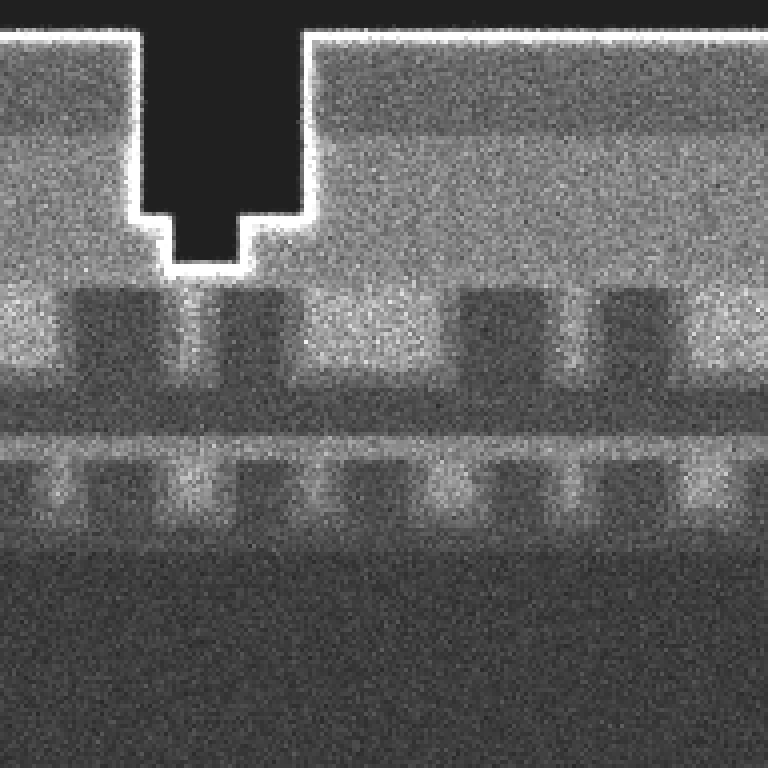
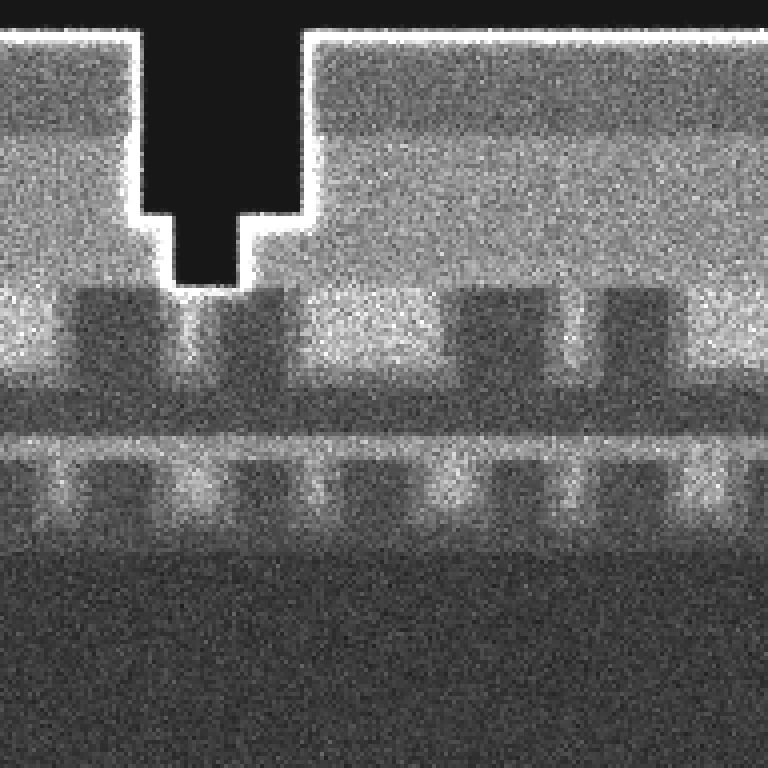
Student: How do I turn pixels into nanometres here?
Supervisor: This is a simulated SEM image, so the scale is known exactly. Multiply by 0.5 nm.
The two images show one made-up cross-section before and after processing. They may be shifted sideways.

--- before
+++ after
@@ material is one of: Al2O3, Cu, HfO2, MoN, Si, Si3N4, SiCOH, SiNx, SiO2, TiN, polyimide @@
Al2O3 removed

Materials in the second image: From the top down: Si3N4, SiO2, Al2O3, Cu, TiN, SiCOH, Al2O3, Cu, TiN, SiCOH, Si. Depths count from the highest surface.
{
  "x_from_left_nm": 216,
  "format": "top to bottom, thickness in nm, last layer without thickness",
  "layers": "Si3N4 52, SiO2 64, Al2O3 12, Cu 40, TiN 10, SiCOH 24, Al2O3 12, Cu 24, TiN 10, SiCOH 12, Si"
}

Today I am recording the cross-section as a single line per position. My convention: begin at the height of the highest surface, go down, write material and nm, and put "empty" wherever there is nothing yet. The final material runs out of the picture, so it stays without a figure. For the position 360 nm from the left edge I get Si3N4 52, SiO2 64, Al2O3 12, Cu 40, TiN 10, SiCOH 24, Al2O3 12, Cu 24, TiN 10, SiCOH 12, Si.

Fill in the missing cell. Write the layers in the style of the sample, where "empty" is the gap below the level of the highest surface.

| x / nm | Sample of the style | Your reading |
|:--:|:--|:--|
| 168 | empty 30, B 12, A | Si3N4 52, SiO2 64, Al2O3 12, Cu 40, TiN 10, SiCOH 24, Al2O3 12, TiN 34, SiCOH 12, Si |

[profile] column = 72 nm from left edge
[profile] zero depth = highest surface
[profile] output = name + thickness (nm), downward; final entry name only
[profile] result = empty 92, SiO2 24, Al2O3 12, SiCOH 74, Al2O3 12, SiCOH 46, Si